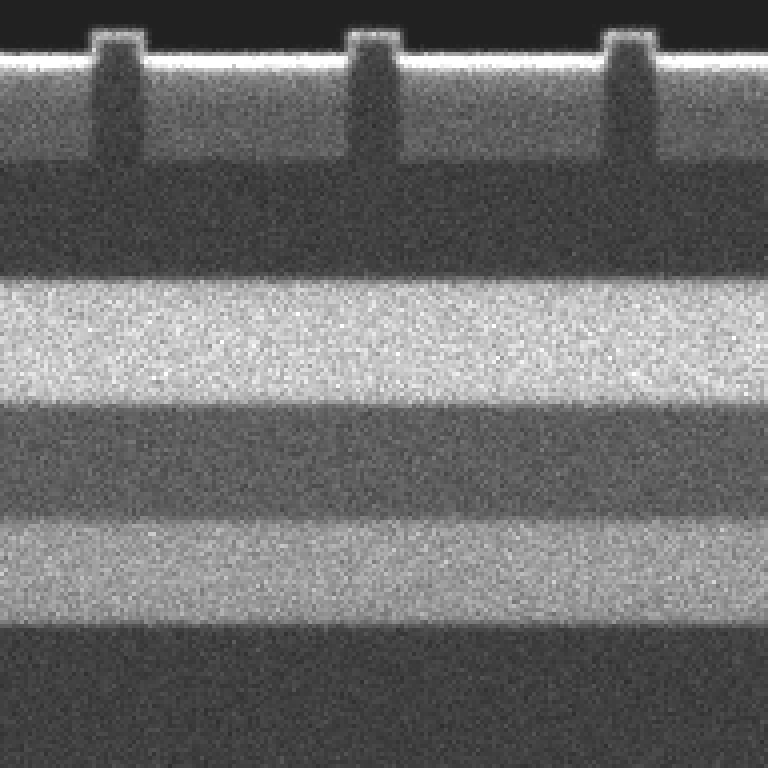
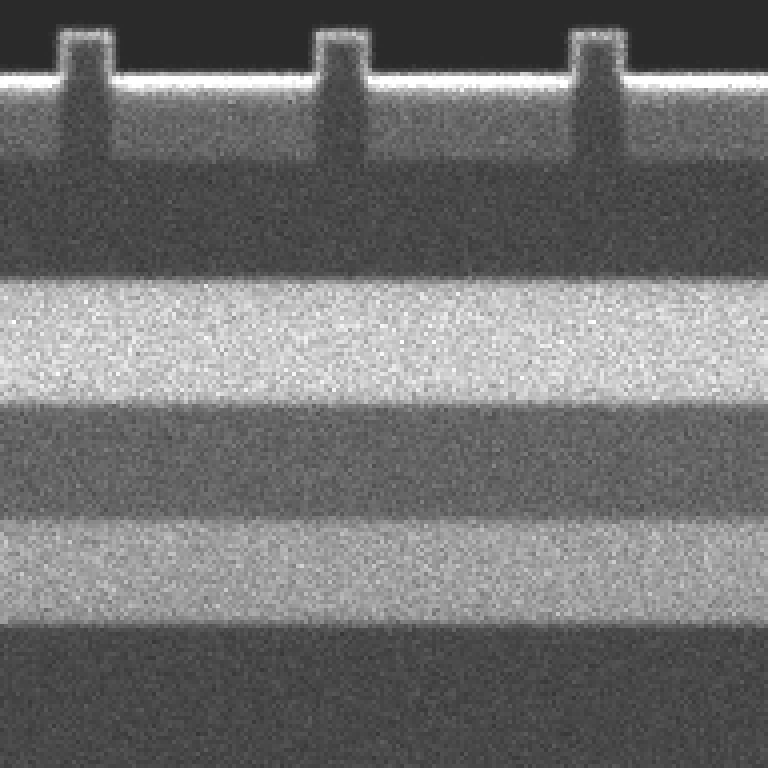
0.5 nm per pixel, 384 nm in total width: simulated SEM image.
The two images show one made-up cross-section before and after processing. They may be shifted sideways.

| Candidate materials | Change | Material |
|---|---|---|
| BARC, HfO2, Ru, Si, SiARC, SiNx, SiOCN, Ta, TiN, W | removed | SiARC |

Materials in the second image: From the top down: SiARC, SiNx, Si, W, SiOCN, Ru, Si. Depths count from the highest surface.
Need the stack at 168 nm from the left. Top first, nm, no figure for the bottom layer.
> Si 124, W 62, SiOCN 58, Ru 52, Si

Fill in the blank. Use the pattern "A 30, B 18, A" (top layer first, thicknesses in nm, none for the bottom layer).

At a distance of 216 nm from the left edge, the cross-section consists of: empty 22, SiARC 12, SiNx 30, Si 60, W 62, SiOCN 58, Ru 52, Si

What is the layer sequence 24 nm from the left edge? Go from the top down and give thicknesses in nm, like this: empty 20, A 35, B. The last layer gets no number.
empty 22, SiARC 12, SiNx 30, Si 60, W 62, SiOCN 58, Ru 52, Si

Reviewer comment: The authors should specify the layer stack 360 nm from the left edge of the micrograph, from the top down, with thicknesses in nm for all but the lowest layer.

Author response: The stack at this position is empty 22, SiARC 12, SiNx 30, Si 60, W 62, SiOCN 58, Ru 52, Si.